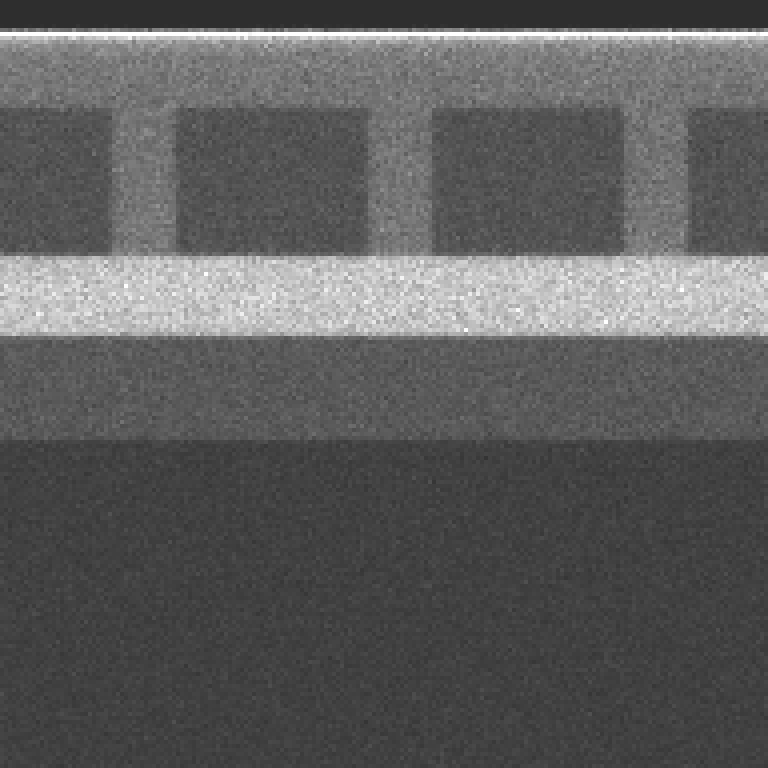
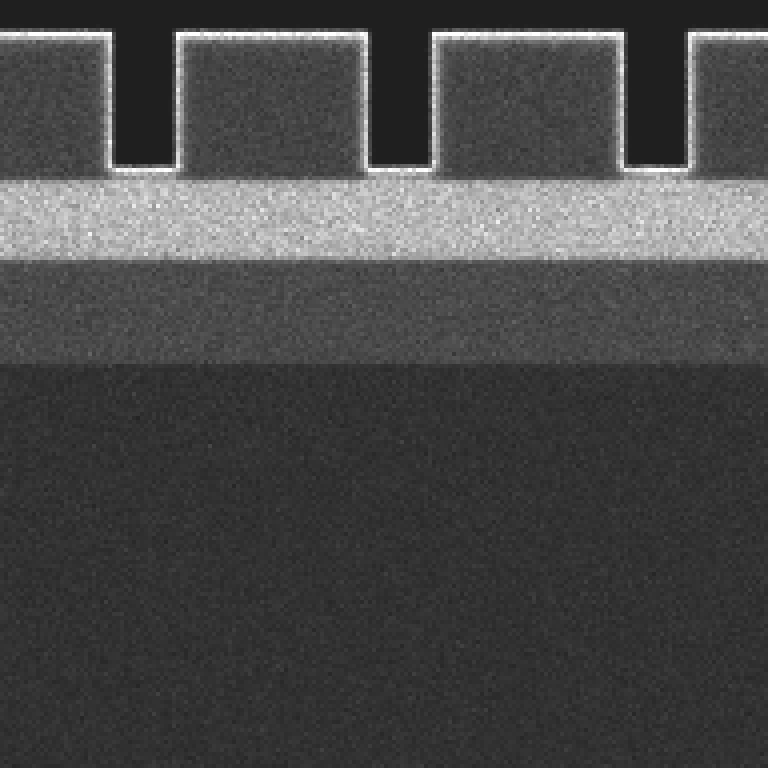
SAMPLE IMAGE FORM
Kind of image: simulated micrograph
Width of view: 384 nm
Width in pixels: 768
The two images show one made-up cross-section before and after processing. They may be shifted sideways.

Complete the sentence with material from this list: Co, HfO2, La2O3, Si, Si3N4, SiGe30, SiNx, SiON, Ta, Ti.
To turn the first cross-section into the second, Co must be removed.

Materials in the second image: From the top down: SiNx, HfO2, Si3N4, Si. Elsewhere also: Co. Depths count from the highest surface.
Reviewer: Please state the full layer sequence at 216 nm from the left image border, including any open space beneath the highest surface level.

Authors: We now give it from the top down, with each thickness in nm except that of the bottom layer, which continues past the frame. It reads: SiNx 74, HfO2 40, Si3N4 52, Si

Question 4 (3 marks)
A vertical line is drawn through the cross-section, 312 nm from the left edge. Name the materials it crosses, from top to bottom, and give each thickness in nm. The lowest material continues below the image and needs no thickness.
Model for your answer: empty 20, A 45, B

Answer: empty 68, Co 6, HfO2 40, Si3N4 52, Si